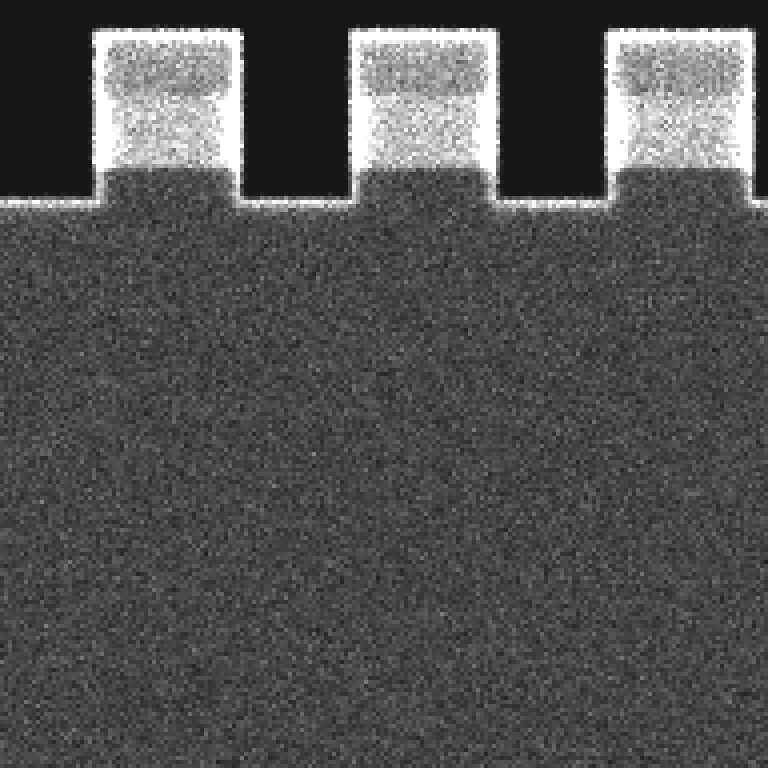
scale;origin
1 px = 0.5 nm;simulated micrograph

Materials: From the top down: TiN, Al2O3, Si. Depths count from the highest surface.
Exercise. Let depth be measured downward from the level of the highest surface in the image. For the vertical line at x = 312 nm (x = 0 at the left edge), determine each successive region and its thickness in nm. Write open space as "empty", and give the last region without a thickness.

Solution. TiN 32, Al2O3 36, Si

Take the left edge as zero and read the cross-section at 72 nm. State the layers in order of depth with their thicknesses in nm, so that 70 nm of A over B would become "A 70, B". TiN 32, Al2O3 36, Si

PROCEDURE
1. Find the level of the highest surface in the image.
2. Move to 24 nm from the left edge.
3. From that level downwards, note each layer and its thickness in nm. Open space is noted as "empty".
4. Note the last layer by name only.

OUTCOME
empty 84, Si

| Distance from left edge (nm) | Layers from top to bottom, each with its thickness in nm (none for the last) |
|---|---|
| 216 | TiN 32, Al2O3 36, Si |